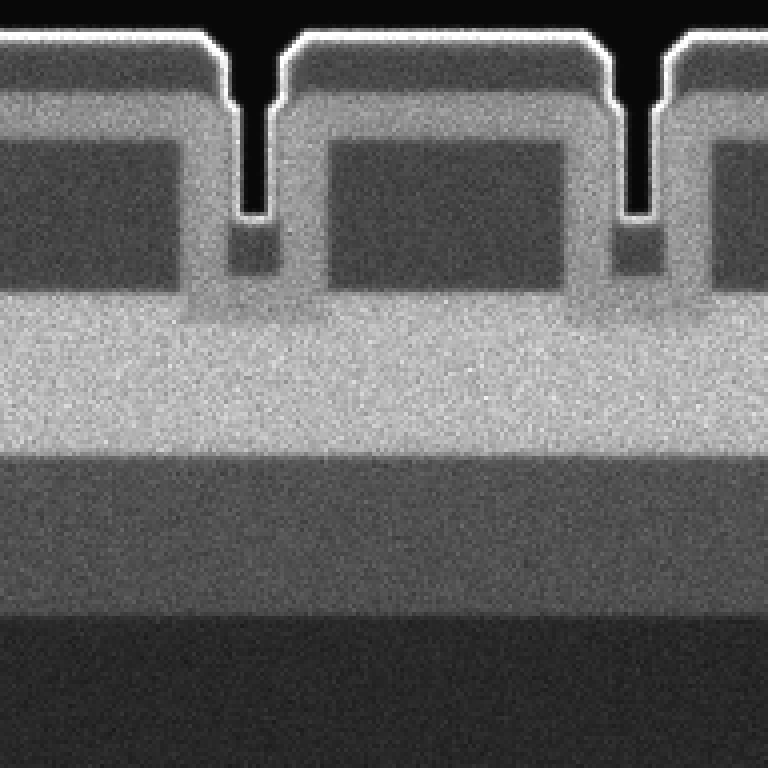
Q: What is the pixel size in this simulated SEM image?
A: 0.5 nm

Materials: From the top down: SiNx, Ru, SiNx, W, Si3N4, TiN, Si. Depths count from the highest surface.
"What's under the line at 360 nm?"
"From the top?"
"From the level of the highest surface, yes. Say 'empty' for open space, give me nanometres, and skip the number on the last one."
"SiNx 30, Ru 24, SiNx 76, W 82, Si3N4 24, TiN 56, Si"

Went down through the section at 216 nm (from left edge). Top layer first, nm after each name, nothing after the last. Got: SiNx 30, Ru 24, SiNx 76, W 82, Si3N4 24, TiN 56, Si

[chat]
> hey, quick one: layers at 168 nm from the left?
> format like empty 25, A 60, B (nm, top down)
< SiNx 30, Ru 24, SiNx 76, W 82, Si3N4 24, TiN 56, Si